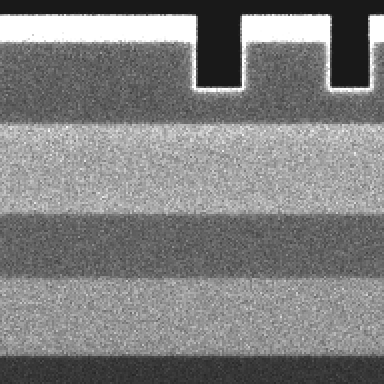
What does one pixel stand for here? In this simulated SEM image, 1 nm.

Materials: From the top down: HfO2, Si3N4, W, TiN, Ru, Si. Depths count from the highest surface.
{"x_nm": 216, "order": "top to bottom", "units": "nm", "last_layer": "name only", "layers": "empty 72, Si3N4 36, W 90, TiN 64, Ru 78, Si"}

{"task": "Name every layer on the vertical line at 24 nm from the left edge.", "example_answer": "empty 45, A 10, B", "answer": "HfO2 26, Si3N4 82, W 90, TiN 64, Ru 78, Si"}